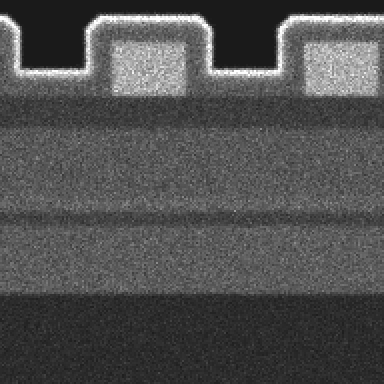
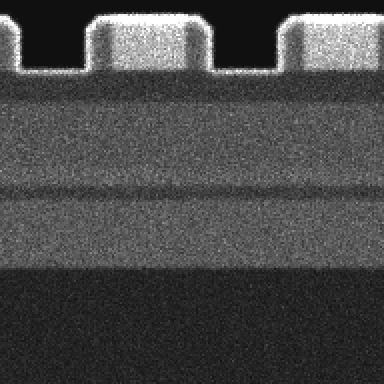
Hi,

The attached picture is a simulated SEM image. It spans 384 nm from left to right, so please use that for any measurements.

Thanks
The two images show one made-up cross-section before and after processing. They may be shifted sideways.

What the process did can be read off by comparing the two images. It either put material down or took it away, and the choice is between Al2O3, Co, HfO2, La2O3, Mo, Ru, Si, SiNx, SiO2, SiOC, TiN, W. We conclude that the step removed SiO2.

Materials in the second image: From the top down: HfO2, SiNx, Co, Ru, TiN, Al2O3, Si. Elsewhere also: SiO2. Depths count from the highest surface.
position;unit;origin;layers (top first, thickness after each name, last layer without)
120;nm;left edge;HfO2 54, SiNx 32, Co 68, Ru 16, TiN 14, Al2O3 68, Si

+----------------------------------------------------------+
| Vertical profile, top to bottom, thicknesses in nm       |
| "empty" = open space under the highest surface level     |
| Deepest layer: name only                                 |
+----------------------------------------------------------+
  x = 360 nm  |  HfO2 54, SiNx 32, Co 68, Ru 16, TiN 14, Al2O3 68, Si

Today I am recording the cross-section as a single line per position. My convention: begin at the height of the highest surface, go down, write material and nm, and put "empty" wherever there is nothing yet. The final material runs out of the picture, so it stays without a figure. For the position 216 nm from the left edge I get empty 54, SiNx 32, Co 68, Ru 16, TiN 14, Al2O3 68, Si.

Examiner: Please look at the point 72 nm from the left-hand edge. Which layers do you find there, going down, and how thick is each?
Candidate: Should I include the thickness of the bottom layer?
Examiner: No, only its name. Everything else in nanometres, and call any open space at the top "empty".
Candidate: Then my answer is empty 54, SiNx 32, Co 68, Ru 16, TiN 14, Al2O3 68, Si